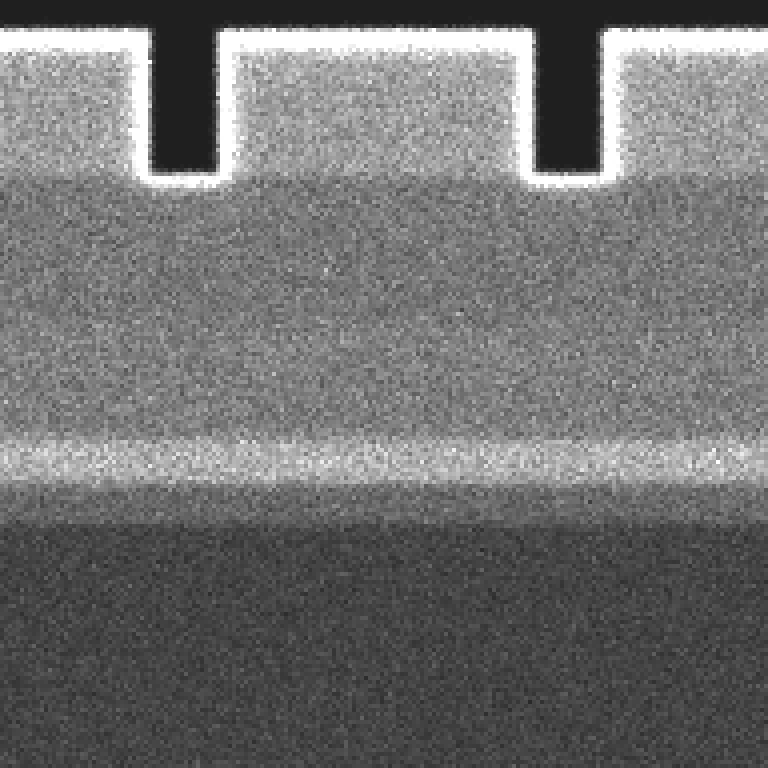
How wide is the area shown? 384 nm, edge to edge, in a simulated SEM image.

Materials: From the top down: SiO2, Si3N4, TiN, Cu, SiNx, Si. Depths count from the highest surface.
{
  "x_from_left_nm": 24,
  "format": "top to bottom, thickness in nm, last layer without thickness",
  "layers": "SiO2 72, Si3N4 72, TiN 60, Cu 22, SiNx 20, Si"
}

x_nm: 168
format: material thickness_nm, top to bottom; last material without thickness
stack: SiO2 72, Si3N4 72, TiN 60, Cu 22, SiNx 20, Si